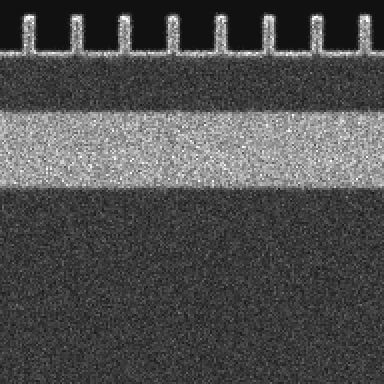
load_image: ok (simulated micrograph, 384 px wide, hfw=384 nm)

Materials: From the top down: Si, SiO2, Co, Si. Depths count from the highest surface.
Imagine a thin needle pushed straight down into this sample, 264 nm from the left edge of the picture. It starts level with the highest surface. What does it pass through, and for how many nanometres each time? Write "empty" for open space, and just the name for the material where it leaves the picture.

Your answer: Si 96, SiO2 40, Co 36, Si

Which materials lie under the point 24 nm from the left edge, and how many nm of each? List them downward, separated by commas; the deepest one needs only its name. Si 96, SiO2 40, Co 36, Si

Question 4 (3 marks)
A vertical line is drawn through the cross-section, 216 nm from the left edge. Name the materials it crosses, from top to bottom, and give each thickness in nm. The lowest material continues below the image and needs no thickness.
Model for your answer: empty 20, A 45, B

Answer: Si 96, SiO2 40, Co 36, Si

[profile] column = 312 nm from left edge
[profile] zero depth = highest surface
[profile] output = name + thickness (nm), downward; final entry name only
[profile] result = Si 96, SiO2 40, Co 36, Si